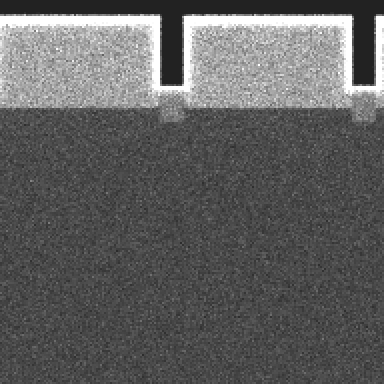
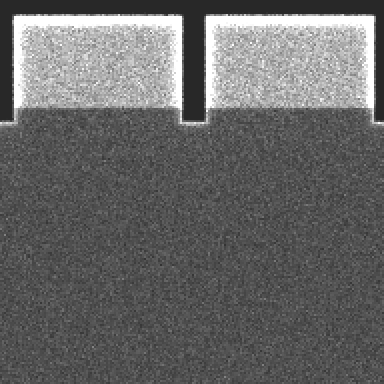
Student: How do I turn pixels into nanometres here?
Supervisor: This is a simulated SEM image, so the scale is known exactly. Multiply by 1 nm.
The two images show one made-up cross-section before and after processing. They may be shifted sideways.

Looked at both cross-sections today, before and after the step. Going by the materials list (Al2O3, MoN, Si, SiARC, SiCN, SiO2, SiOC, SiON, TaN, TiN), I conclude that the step removed SiARC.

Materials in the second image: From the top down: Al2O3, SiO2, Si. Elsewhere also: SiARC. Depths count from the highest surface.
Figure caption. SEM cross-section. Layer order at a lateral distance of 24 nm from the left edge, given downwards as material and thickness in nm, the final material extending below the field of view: Al2O3 10, SiO2 82, Si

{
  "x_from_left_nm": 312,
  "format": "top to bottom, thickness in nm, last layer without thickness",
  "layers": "Al2O3 10, SiO2 82, Si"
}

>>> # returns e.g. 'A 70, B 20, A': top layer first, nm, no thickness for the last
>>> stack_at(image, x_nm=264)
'Al2O3 10, SiO2 82, Si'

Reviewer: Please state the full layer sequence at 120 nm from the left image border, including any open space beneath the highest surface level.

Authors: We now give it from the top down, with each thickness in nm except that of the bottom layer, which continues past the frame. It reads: Al2O3 10, SiO2 82, Si